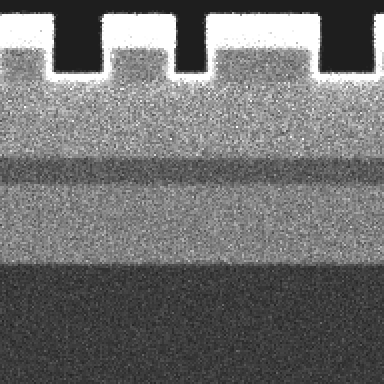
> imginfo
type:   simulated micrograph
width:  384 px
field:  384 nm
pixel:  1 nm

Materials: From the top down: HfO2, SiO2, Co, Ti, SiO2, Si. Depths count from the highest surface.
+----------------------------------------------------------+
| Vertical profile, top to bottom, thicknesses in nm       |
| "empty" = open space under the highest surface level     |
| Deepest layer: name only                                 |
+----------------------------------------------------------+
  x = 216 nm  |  HfO2 32, SiO2 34, Co 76, Ti 26, SiO2 80, Si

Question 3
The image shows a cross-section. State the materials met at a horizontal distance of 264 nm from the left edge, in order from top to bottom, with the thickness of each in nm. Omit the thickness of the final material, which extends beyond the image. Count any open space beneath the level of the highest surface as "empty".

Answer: HfO2 32, SiO2 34, Co 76, Ti 26, SiO2 80, Si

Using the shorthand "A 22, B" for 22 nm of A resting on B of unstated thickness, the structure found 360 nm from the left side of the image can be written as empty 58, SiO2 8, Co 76, Ti 26, SiO2 80, Si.